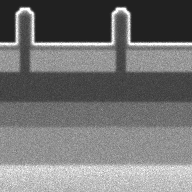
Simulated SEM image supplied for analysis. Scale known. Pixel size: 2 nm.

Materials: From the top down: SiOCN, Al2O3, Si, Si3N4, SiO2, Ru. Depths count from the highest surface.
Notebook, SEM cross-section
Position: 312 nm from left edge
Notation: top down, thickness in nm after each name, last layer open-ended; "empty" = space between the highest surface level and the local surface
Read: empty 70, SiOCN 14, Al2O3 44, Si 60, Si3N4 50, SiO2 76, Ru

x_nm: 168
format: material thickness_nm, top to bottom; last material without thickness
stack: empty 70, SiOCN 14, Al2O3 44, Si 60, Si3N4 50, SiO2 76, Ru